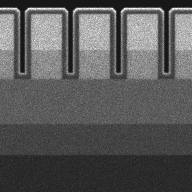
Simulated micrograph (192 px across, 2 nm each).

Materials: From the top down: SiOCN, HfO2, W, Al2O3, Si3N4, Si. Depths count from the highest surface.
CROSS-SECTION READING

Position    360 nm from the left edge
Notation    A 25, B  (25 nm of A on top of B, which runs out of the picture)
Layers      SiOCN 12, HfO2 72, W 58, Al2O3 90, Si3N4 62, Si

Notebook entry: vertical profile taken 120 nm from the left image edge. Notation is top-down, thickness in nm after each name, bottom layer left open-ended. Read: SiOCN 12, HfO2 72, W 58, Al2O3 90, Si3N4 62, Si